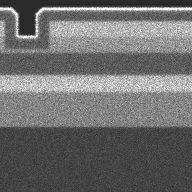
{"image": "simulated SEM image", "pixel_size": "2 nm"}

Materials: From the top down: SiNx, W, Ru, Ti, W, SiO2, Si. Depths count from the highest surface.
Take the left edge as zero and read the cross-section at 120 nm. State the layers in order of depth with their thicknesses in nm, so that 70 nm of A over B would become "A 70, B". SiNx 26, W 32, Ru 32, Ti 44, W 34, SiO2 70, Si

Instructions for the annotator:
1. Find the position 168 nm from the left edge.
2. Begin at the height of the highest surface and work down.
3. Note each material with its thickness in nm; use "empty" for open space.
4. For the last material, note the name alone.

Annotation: SiNx 26, W 32, Ru 32, Ti 44, W 34, SiO2 70, Si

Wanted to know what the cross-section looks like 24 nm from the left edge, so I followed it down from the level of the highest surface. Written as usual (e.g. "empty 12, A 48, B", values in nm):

empty 2, SiNx 80, Ru 8, Ti 44, W 34, SiO2 70, Si